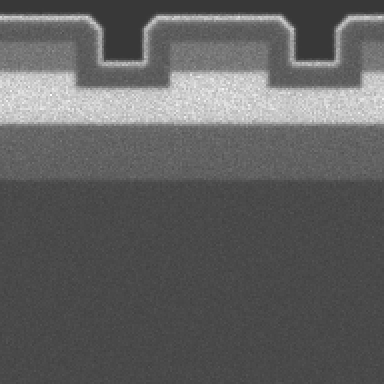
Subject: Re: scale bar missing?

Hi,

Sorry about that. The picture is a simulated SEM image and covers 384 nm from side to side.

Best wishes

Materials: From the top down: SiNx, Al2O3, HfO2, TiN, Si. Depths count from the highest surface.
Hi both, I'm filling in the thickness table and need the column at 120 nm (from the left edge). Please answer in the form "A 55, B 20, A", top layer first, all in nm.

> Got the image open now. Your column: empty 46, SiNx 26, HfO2 36, TiN 56, Si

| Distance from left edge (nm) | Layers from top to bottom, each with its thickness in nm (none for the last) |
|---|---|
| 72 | SiNx 26, Al2O3 30, HfO2 52, TiN 56, Si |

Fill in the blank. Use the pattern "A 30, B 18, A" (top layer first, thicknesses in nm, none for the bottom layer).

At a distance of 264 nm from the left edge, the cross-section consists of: SiNx 26, Al2O3 30, HfO2 52, TiN 56, Si